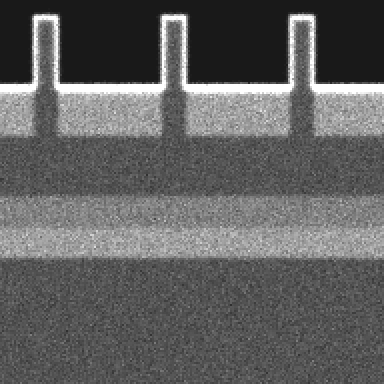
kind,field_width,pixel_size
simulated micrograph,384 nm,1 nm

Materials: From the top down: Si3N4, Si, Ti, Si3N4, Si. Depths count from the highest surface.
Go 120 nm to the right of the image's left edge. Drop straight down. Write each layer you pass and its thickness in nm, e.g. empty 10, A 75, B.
empty 70, Si3N4 50, Si 60, Ti 32, Si3N4 30, Si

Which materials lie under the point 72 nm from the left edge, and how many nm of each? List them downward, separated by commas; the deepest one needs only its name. empty 70, Si3N4 50, Si 60, Ti 32, Si3N4 30, Si